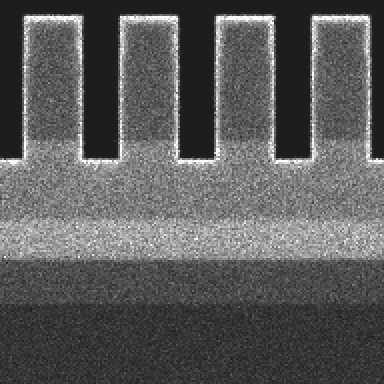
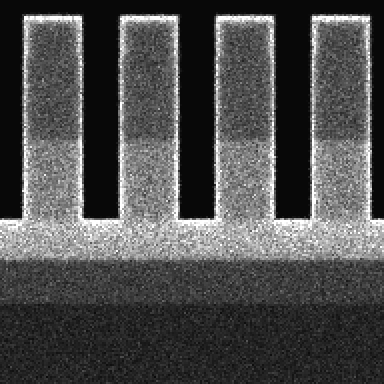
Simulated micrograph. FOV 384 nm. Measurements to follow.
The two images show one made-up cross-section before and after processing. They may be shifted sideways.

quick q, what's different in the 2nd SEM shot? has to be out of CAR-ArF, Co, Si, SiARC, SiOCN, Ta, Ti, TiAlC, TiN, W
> Co removed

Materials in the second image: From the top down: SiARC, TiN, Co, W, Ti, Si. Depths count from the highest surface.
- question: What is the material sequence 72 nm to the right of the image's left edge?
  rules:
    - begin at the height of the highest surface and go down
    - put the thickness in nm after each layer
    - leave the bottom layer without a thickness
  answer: SiARC 40, TiN 84, Co 80, W 40, Ti 44, Si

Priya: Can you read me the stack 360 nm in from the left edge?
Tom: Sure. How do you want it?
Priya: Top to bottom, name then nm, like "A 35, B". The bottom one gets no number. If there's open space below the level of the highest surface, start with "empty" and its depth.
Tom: SiARC 40, TiN 84, Co 80, W 40, Ti 44, Si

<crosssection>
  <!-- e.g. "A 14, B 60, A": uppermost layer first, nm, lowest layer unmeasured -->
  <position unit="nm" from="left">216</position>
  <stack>SiARC 40, TiN 84, Co 80, W 40, Ti 44, Si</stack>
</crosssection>